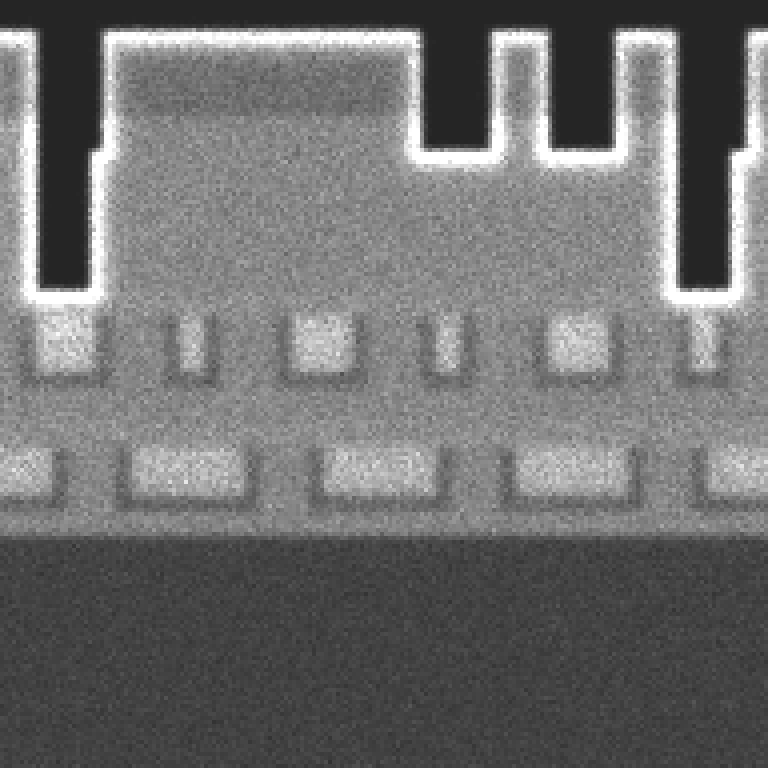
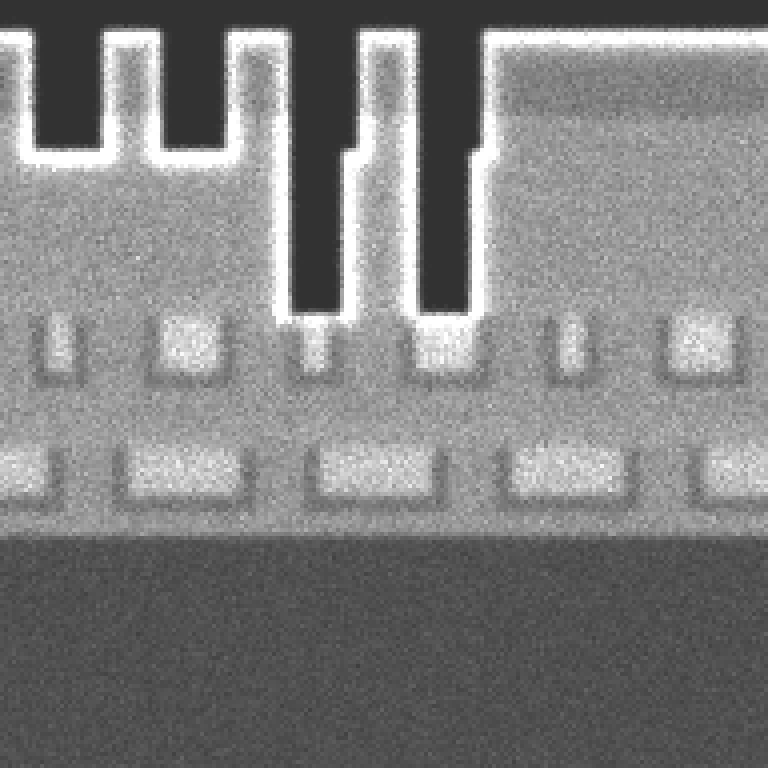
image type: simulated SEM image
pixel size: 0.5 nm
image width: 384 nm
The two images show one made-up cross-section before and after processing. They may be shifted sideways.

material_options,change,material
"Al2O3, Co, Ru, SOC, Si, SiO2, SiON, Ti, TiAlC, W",removed,Al2O3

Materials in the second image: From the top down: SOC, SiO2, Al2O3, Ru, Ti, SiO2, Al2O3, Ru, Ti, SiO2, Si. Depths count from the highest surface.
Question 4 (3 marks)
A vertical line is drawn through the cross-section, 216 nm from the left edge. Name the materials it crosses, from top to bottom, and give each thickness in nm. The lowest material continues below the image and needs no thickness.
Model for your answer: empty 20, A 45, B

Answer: empty 142, Ru 28, Ti 8, SiO2 16, Al2O3 14, Ti 32, SiO2 12, Si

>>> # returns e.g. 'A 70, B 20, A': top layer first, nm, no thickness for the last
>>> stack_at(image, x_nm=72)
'SOC 42, SiO2 88, Al2O3 12, Ti 36, SiO2 16, Al2O3 14, Ru 24, Ti 8, SiO2 12, Si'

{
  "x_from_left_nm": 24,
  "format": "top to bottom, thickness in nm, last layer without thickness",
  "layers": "empty 60, SiO2 70, Al2O3 12, Ru 28, Ti 8, SiO2 16, Al2O3 14, Ti 32, SiO2 12, Si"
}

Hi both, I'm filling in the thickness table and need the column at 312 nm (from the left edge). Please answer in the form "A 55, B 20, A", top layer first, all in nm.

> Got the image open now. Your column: SOC 42, SiO2 88, Al2O3 12, SiO2 52, Al2O3 14, Ti 32, SiO2 12, Si